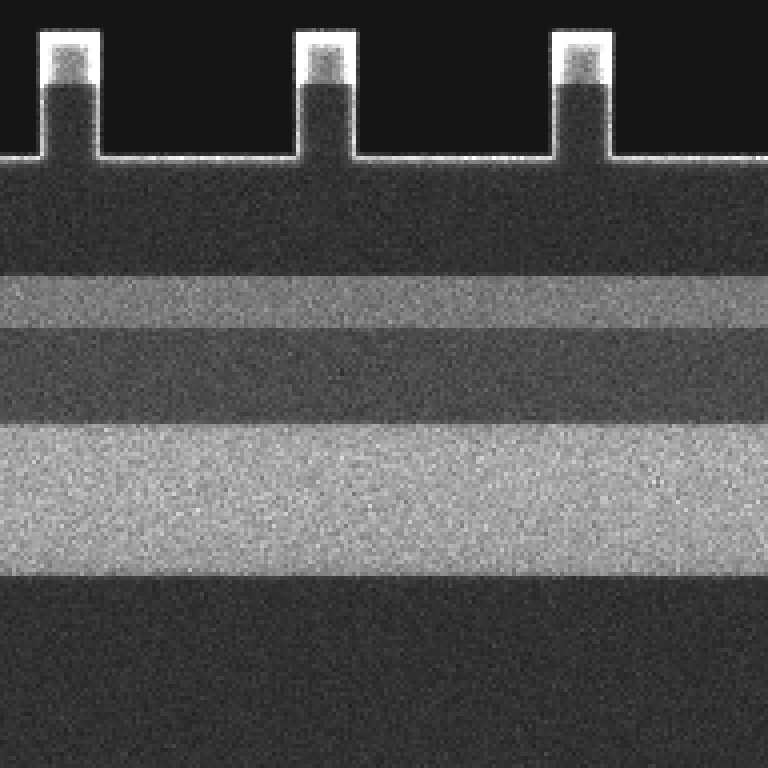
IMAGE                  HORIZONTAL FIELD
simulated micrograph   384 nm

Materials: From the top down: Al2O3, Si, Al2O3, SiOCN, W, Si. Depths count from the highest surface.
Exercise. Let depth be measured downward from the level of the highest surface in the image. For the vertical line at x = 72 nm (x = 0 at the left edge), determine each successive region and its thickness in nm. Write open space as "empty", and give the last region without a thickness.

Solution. empty 62, Si 60, Al2O3 26, SiOCN 48, W 76, Si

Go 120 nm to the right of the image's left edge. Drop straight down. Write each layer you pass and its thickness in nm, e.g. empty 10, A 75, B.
empty 62, Si 60, Al2O3 26, SiOCN 48, W 76, Si